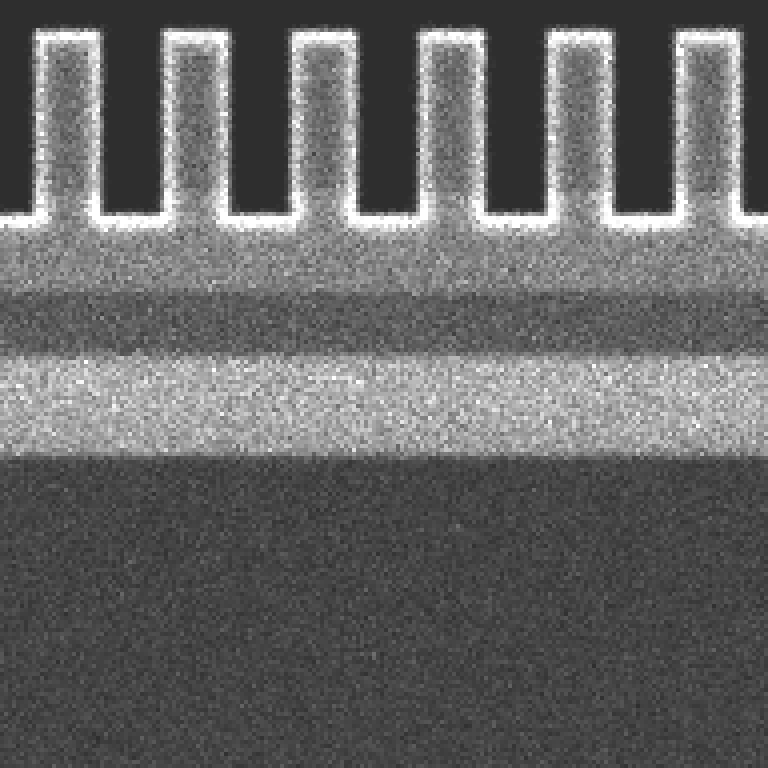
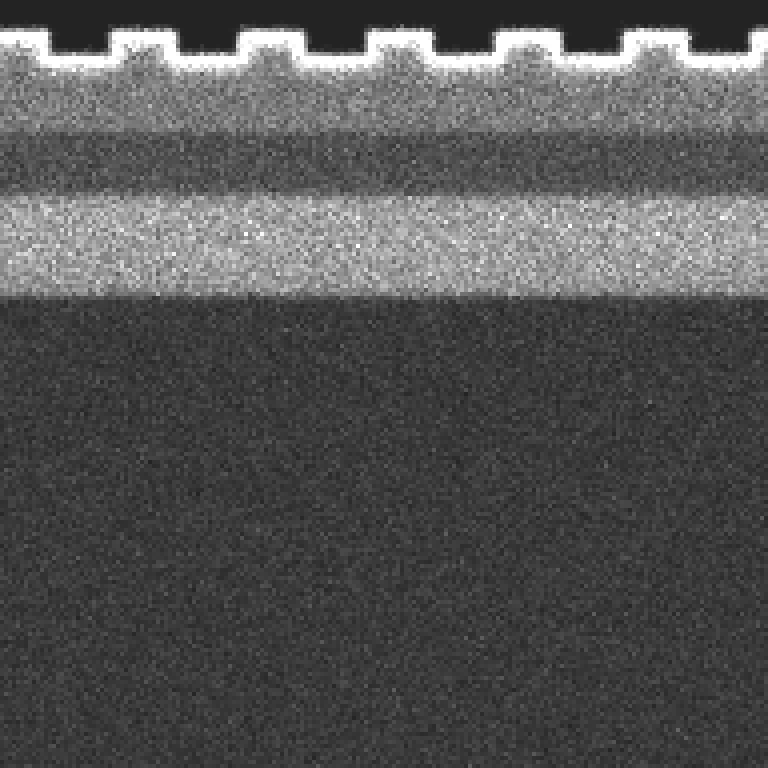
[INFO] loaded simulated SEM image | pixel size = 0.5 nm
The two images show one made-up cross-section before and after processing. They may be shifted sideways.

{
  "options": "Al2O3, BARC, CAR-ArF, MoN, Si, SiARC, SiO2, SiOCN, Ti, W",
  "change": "removed",
  "material": "SiARC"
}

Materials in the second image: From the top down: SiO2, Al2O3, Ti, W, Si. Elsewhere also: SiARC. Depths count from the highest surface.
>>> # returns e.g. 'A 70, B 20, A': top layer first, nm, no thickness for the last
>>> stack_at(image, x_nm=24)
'empty 12, SiO2 18, Al2O3 20, Ti 32, W 50, Si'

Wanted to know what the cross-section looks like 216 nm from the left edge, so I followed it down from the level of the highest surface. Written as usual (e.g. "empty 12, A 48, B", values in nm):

empty 12, SiO2 18, Al2O3 20, Ti 32, W 50, Si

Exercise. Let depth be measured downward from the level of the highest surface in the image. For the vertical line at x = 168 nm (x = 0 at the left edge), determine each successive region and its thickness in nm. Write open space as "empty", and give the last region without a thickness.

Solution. empty 12, SiO2 18, Al2O3 20, Ti 32, W 50, Si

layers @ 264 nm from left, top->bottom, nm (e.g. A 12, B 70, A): SiO2 30, Al2O3 20, Ti 32, W 50, Si